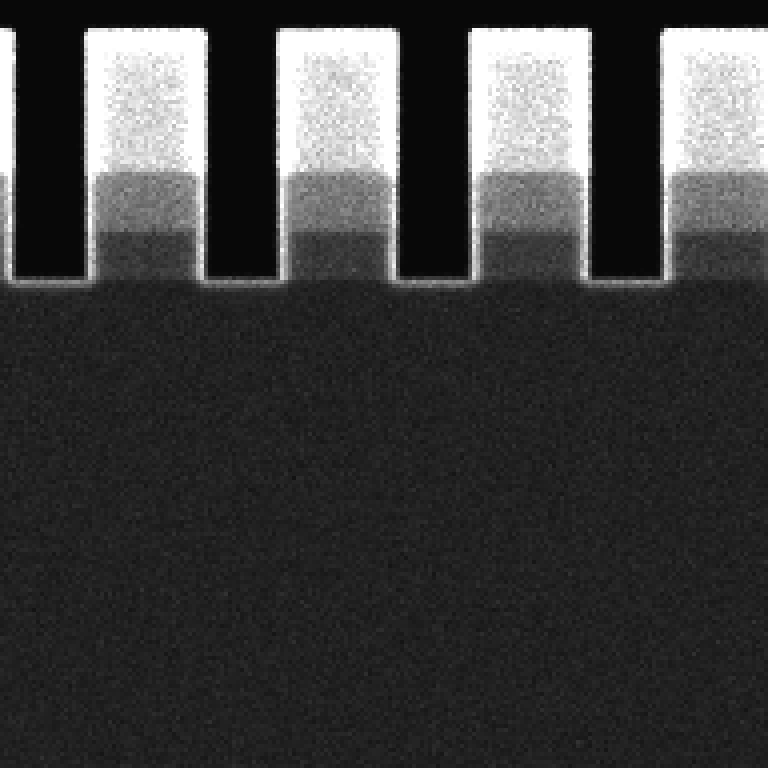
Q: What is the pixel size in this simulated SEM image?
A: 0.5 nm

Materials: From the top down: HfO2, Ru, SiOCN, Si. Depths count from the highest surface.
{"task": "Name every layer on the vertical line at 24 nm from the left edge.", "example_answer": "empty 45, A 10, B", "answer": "empty 124, Si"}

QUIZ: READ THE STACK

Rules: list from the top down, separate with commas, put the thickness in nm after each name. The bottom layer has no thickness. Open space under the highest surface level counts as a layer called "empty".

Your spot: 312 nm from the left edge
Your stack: empty 124, Si